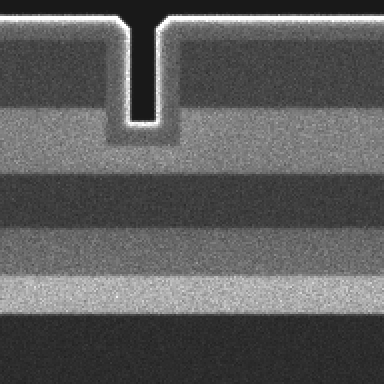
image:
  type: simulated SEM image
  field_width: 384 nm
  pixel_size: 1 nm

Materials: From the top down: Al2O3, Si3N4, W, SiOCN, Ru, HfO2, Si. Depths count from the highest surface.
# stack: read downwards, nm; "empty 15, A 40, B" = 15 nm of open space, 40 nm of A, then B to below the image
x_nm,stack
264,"Al2O3 24, Si3N4 68, W 66, SiOCN 54, Ru 48, HfO2 38, Si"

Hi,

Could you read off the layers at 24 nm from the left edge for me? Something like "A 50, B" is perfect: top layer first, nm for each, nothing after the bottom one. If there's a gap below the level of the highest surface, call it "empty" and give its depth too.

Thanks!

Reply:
Al2O3 24, Si3N4 68, W 66, SiOCN 54, Ru 48, HfO2 38, Si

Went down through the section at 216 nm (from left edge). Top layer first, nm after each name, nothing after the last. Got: Al2O3 24, Si3N4 68, W 66, SiOCN 54, Ru 48, HfO2 38, Si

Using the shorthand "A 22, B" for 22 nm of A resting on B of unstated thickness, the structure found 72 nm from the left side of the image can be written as Al2O3 24, Si3N4 68, W 66, SiOCN 54, Ru 48, HfO2 38, Si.